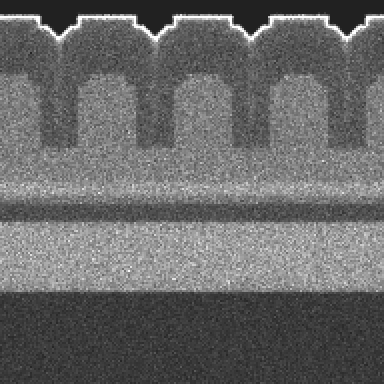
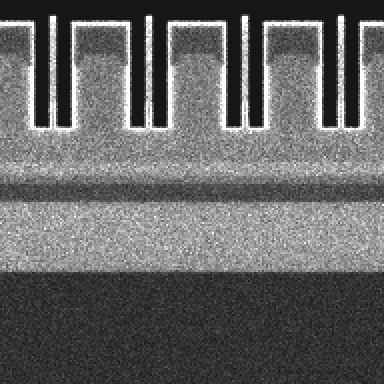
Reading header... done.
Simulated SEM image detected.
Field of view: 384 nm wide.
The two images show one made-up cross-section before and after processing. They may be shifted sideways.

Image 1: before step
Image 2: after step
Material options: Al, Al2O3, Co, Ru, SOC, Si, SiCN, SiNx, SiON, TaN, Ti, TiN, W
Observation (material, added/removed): TiN, removed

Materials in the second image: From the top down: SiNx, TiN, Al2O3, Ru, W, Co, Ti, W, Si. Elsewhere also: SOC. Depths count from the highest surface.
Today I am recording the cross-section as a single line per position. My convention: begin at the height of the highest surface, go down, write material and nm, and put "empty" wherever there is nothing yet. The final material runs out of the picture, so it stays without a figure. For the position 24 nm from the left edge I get empty 6, SiNx 32, TiN 8, Al2O3 66, Ru 34, W 14, Co 8, Ti 18, W 70, Si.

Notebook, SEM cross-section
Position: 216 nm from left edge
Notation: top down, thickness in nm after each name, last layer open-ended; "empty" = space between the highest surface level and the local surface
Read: empty 6, SiNx 32, TiN 8, Al2O3 66, Ru 34, W 14, Co 8, Ti 18, W 70, Si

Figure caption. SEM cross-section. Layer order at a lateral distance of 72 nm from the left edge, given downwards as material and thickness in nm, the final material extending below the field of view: empty 6, SiNx 32, TiN 12, Al2O3 62, Ru 34, W 14, Co 8, Ti 18, W 70, Si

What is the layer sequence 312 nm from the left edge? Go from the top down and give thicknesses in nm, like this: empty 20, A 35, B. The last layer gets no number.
empty 6, SiNx 32, TiN 8, Al2O3 66, Ru 34, W 14, Co 8, Ti 18, W 70, Si